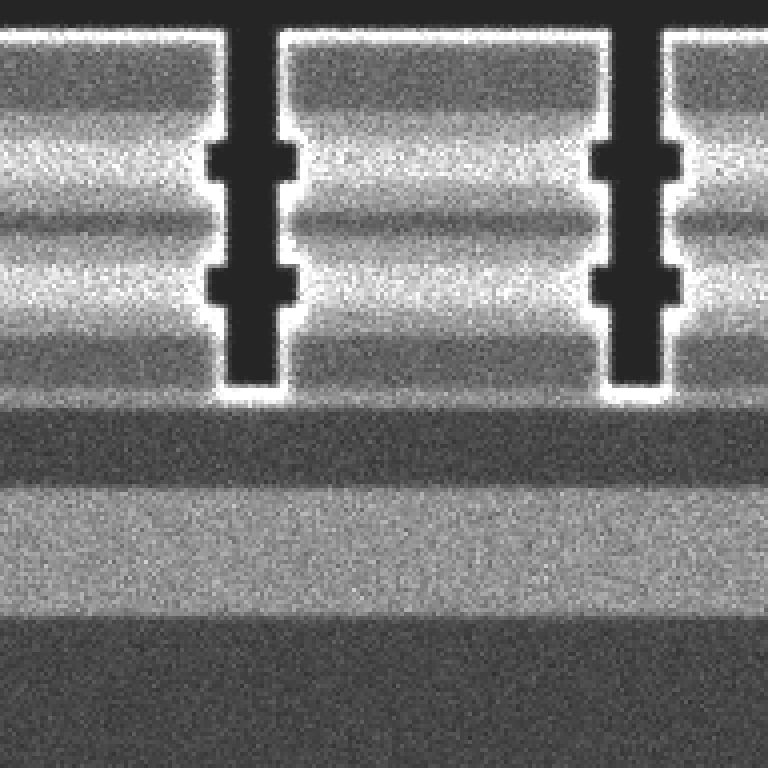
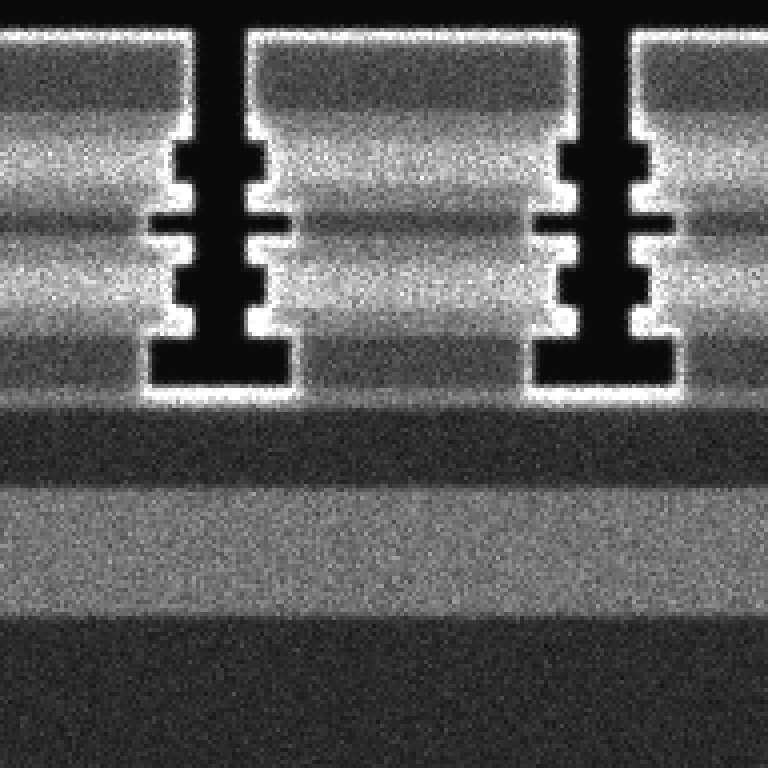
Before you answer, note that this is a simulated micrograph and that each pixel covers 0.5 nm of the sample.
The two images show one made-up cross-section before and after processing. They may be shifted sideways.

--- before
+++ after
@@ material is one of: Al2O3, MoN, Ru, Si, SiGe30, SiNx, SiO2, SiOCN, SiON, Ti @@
SiOCN removed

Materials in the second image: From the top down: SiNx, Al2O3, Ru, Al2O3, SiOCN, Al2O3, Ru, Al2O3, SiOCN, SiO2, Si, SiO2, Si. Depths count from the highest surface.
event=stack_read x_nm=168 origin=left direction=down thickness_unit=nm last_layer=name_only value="SiNx 40, Al2O3 14, Ru 22, Al2O3 14, SiOCN 12, Al2O3 14, Ru 22, Al2O3 14, SiOCN 26, SiO2 10, Si 40, SiO2 64, Si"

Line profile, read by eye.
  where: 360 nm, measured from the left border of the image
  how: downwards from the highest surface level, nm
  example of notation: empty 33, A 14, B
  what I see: SiNx 40, Al2O3 14, Ru 22, Al2O3 14, SiOCN 12, Al2O3 14, Ru 22, Al2O3 14, SiOCN 26, SiO2 10, Si 40, SiO2 64, Si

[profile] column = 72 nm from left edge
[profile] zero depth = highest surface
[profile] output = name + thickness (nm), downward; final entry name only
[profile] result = SiNx 40, Al2O3 14, Ru 22, Al2O3 14, SiOCN 12, Al2O3 14, Ru 22, Al2O3 14, SiOCN 26, SiO2 10, Si 40, SiO2 64, Si